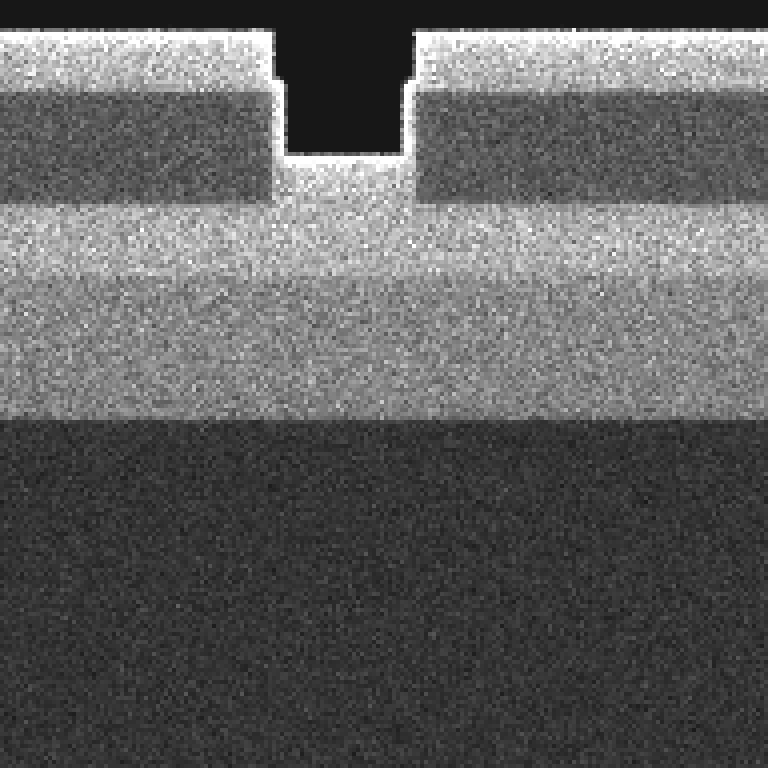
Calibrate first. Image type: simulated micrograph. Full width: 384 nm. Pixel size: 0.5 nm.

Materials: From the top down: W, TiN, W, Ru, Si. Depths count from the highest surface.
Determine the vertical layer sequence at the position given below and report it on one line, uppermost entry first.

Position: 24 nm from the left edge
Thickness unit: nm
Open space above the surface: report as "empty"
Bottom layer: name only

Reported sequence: W 30, TiN 56, W 36, Ru 72, Si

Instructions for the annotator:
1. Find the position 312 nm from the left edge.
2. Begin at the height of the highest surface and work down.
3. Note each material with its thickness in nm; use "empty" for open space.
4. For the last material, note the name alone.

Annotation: W 30, TiN 56, W 36, Ru 72, Si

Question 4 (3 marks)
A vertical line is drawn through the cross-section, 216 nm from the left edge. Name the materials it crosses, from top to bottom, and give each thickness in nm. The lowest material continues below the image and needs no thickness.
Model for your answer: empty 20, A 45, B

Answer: W 30, TiN 56, W 36, Ru 72, Si